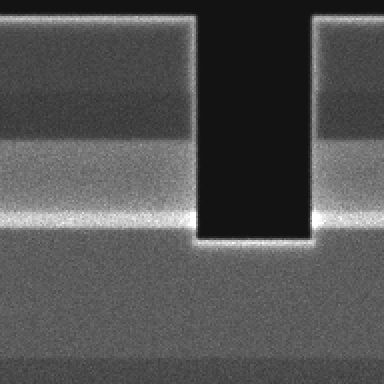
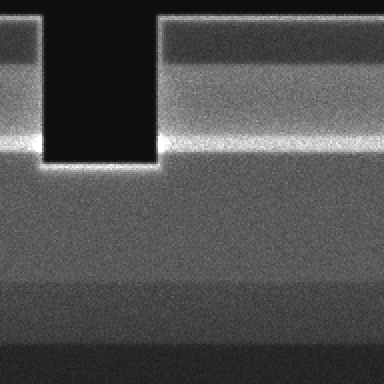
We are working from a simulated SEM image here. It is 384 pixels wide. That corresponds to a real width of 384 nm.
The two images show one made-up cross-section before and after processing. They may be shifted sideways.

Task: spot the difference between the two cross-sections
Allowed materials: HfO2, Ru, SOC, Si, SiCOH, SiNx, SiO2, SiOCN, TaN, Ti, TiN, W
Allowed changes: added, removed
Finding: removed SOC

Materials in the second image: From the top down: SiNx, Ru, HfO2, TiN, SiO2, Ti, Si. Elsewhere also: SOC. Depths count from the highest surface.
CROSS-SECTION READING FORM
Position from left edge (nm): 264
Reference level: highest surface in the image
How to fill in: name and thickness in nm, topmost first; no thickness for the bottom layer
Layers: SiNx 48, Ru 72, HfO2 16, TiN 12, SiO2 118, Ti 62, Si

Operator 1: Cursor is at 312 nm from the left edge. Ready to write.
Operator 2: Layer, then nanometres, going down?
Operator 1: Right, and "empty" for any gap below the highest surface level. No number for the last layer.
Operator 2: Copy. SiNx 48, Ru 72, HfO2 16, TiN 12, SiO2 118, Ti 62, Si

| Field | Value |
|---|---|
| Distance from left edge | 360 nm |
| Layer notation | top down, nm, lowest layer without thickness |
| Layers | SiNx 48, Ru 72, HfO2 16, TiN 12, SiO2 118, Ti 62, Si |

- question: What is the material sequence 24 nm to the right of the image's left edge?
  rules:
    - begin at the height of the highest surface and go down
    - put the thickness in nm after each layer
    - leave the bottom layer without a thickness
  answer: SiNx 48, Ru 72, HfO2 16, TiN 12, SiO2 118, Ti 62, Si